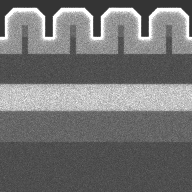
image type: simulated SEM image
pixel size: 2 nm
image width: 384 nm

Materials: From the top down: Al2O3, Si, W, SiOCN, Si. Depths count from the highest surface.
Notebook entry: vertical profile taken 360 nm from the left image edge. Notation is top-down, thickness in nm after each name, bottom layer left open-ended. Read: Al2O3 92, Si 60, W 54, SiOCN 62, Si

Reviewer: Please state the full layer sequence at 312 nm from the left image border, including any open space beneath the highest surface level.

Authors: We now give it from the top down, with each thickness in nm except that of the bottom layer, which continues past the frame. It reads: empty 2, Al2O3 90, Si 60, W 54, SiOCN 62, Si